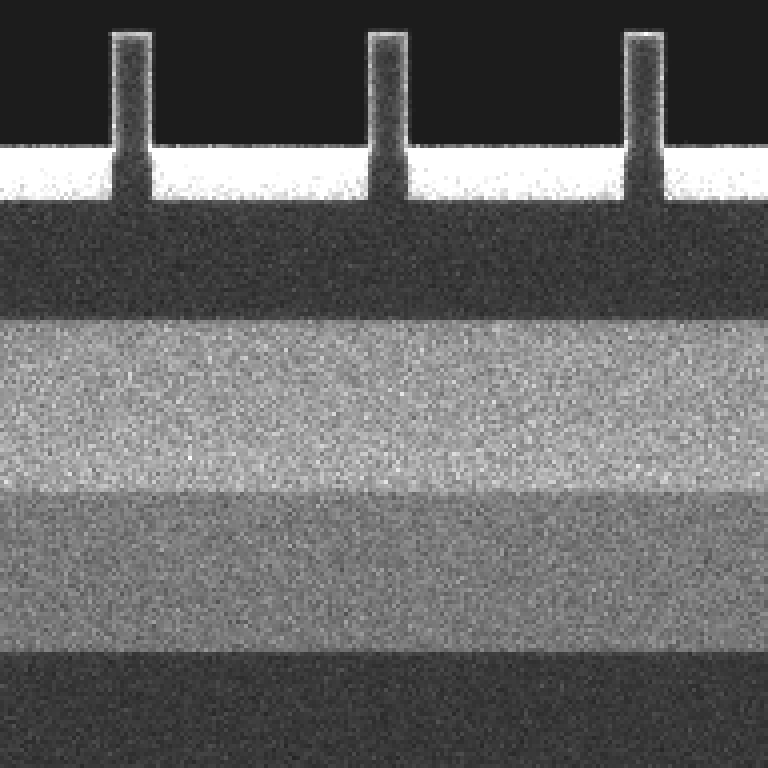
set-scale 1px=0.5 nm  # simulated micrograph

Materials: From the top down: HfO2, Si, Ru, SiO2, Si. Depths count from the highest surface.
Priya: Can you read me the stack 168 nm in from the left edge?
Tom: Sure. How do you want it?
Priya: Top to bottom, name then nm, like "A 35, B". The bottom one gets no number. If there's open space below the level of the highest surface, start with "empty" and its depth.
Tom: empty 58, HfO2 26, Si 60, Ru 86, SiO2 80, Si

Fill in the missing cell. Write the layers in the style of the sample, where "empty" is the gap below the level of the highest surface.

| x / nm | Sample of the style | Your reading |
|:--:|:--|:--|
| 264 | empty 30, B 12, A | empty 58, HfO2 26, Si 60, Ru 86, SiO2 80, Si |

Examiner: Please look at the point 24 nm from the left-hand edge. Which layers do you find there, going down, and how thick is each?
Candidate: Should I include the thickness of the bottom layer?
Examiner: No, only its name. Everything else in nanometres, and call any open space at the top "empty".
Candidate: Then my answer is empty 58, HfO2 26, Si 60, Ru 86, SiO2 80, Si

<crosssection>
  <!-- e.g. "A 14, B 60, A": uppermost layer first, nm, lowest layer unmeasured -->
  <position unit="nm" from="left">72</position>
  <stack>Si 144, Ru 86, SiO2 80, Si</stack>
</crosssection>